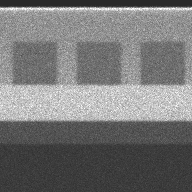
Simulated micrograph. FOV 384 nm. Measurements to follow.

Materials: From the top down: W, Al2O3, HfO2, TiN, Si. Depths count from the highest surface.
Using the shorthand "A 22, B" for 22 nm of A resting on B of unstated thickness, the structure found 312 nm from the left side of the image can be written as W 68, Al2O3 86, HfO2 72, TiN 46, Si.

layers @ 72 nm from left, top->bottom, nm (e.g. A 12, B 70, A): W 68, Al2O3 86, HfO2 72, TiN 46, Si